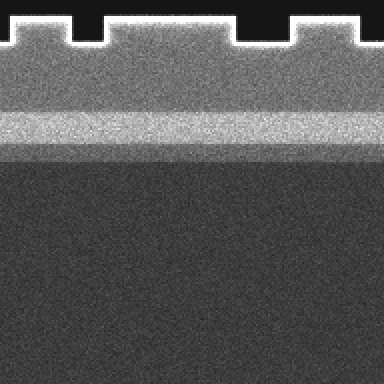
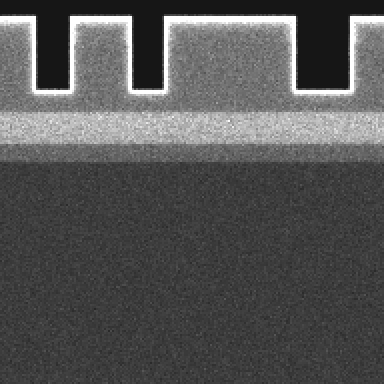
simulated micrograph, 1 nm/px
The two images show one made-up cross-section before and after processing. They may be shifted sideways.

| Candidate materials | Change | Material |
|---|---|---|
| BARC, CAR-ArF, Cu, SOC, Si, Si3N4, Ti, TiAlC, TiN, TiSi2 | removed | Si3N4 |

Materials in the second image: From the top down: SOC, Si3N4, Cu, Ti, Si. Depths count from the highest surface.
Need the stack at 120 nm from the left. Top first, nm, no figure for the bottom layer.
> SOC 26, Si3N4 70, Cu 32, Ti 18, Si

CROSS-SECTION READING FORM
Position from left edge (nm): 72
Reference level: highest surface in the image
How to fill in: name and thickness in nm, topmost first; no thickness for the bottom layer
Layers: SOC 26, Si3N4 70, Cu 32, Ti 18, Si